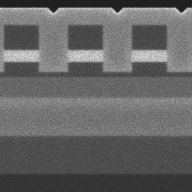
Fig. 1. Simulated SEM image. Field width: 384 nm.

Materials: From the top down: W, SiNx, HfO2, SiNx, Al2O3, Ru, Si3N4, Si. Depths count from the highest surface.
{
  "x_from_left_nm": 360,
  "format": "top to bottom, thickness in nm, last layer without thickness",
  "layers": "empty 10, W 118, SiNx 10, Al2O3 42, Ru 76, Si3N4 76, Si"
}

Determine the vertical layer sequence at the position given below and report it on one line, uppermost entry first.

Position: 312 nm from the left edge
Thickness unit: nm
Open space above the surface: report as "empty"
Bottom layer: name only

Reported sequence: W 34, SiNx 50, HfO2 24, SiNx 30, Al2O3 42, Ru 76, Si3N4 76, Si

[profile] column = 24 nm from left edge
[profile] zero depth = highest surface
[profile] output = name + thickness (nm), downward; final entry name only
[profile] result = W 34, SiNx 50, HfO2 24, SiNx 30, Al2O3 42, Ru 76, Si3N4 76, Si